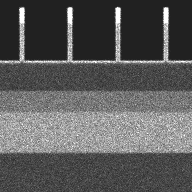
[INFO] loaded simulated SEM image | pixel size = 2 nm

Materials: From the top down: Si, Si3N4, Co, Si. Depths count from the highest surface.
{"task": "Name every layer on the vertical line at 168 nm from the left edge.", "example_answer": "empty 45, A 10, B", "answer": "empty 106, Si 60, Si3N4 42, Co 82, Si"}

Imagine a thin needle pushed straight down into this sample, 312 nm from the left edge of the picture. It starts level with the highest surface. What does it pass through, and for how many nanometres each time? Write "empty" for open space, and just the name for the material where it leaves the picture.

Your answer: empty 106, Si 60, Si3N4 42, Co 82, Si